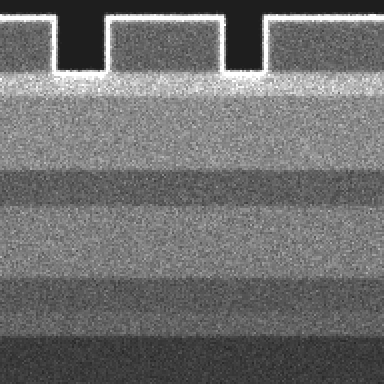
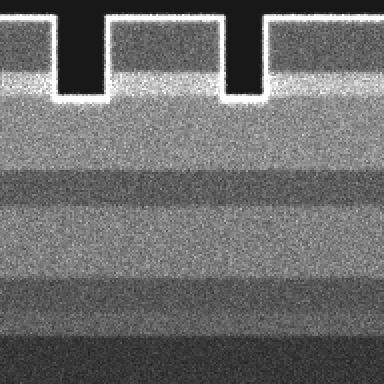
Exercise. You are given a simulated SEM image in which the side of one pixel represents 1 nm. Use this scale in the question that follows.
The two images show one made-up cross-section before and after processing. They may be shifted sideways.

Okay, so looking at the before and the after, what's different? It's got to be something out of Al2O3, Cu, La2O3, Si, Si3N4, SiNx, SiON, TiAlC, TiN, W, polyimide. W, removed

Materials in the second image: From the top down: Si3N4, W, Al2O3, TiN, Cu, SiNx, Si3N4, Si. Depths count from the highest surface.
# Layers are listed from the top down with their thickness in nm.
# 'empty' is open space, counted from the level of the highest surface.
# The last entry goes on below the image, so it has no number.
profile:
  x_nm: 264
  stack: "Si3N4 56, W 24, Al2O3 74, TiN 36, Cu 72, SiNx 34, Si3N4 24, Si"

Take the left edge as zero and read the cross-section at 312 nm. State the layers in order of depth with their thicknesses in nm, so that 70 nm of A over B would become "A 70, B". Si3N4 56, W 24, Al2O3 74, TiN 36, Cu 72, SiNx 34, Si3N4 24, Si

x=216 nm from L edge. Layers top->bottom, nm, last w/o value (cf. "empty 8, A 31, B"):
Si3N4 56, W 24, Al2O3 74, TiN 36, Cu 72, SiNx 34, Si3N4 24, Si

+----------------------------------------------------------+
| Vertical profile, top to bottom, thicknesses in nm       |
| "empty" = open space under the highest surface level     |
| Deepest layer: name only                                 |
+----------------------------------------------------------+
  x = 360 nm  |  Si3N4 56, W 24, Al2O3 74, TiN 36, Cu 72, SiNx 34, Si3N4 24, Si